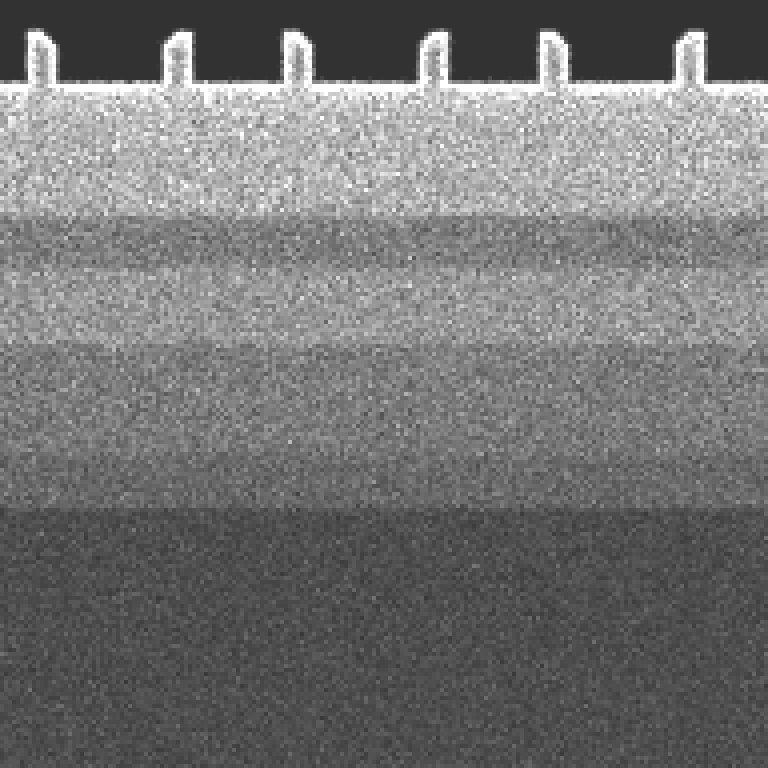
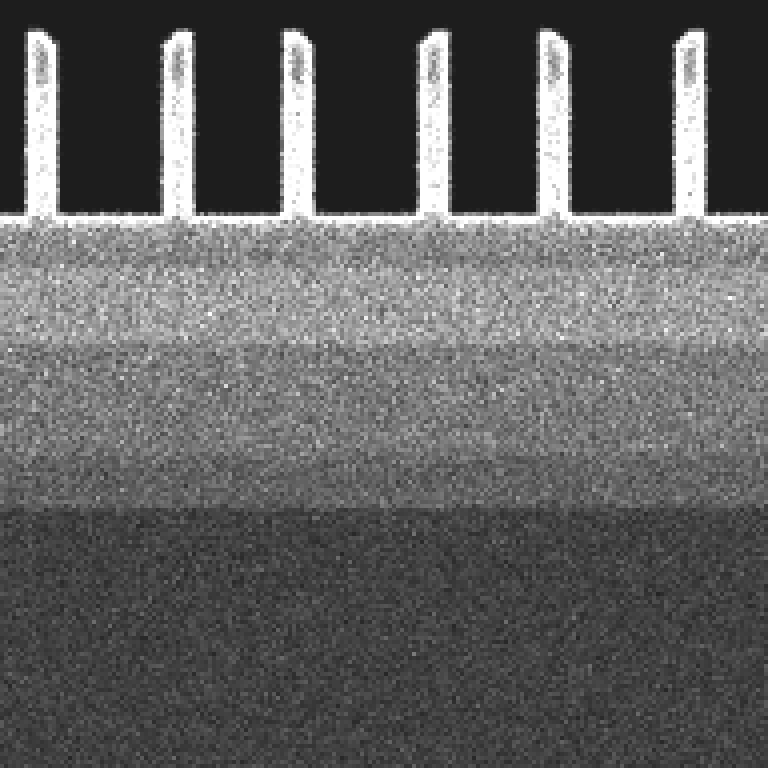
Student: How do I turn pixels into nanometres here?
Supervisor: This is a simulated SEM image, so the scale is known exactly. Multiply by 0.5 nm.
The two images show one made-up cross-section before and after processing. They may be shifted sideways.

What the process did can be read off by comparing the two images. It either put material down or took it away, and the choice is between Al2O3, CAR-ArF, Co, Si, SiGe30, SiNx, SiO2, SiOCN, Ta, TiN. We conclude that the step removed Co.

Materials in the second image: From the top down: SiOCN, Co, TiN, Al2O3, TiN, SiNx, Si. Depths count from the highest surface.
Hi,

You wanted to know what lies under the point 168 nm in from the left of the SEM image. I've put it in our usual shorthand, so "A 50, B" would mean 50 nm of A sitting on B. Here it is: empty 92, TiN 26, Al2O3 38, TiN 56, SiNx 26, Si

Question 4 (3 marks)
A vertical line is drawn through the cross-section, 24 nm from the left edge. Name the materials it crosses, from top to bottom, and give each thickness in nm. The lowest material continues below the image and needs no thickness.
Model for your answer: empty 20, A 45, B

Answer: empty 4, SiOCN 22, Co 66, TiN 26, Al2O3 38, TiN 56, SiNx 26, Si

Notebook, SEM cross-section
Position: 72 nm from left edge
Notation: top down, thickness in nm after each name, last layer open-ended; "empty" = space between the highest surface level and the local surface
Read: empty 92, TiN 26, Al2O3 38, TiN 56, SiNx 26, Si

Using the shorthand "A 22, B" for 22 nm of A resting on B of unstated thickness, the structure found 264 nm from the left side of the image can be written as empty 92, TiN 26, Al2O3 38, TiN 56, SiNx 26, Si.